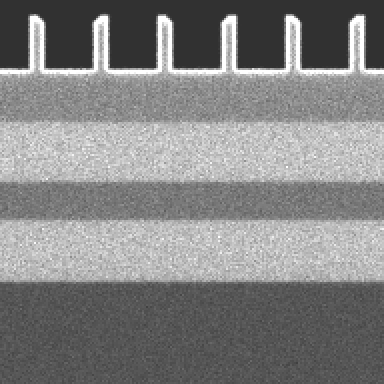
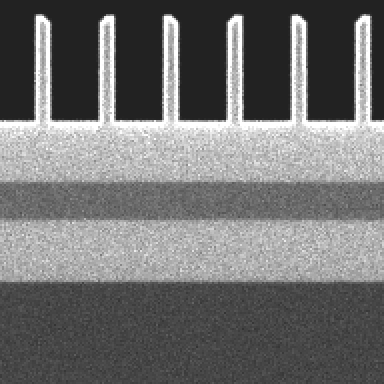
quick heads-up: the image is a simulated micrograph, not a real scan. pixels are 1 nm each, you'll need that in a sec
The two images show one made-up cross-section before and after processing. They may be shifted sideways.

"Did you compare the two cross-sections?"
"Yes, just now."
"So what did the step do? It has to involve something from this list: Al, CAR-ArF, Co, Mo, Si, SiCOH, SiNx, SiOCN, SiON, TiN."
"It removed TiN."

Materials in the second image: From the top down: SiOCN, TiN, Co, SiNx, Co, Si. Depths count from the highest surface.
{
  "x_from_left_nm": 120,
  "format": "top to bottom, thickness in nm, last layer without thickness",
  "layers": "empty 106, Co 60, SiNx 38, Co 62, Si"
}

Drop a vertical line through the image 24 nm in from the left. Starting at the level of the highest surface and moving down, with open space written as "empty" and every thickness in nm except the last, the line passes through empty 106, Co 60, SiNx 38, Co 62, Si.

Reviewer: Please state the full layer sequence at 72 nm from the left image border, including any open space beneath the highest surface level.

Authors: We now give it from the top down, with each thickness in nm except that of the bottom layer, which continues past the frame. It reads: empty 106, Co 60, SiNx 38, Co 62, Si